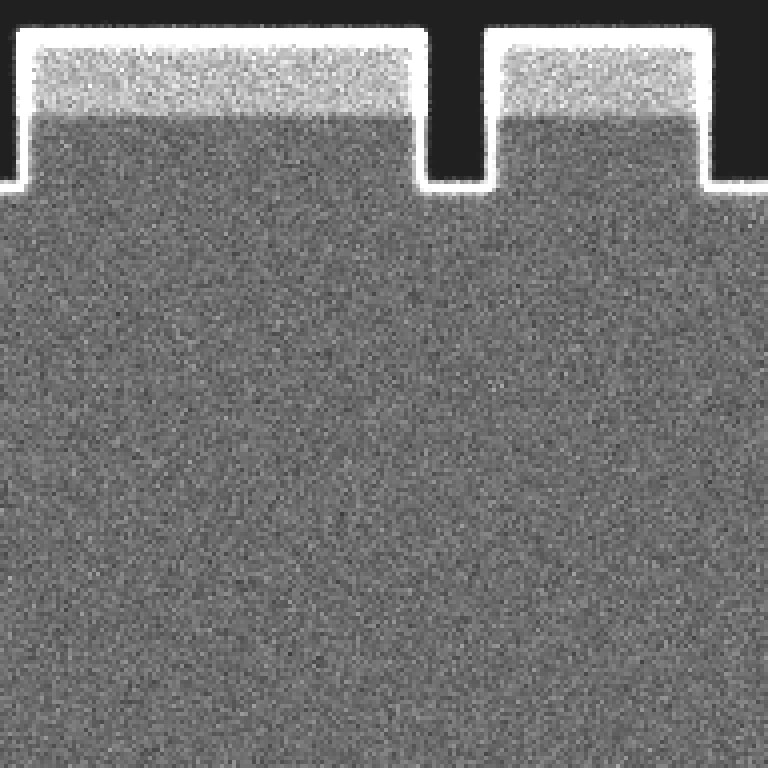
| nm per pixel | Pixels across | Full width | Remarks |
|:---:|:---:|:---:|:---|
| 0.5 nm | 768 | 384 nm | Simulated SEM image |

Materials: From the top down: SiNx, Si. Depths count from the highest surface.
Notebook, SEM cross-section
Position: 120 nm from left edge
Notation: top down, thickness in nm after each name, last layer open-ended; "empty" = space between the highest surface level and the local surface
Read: SiNx 42, Si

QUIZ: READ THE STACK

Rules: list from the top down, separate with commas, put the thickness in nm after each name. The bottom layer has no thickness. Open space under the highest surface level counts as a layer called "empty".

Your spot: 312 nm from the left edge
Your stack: SiNx 42, Si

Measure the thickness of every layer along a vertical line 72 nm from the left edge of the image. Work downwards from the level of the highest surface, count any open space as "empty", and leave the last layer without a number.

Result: SiNx 42, Si